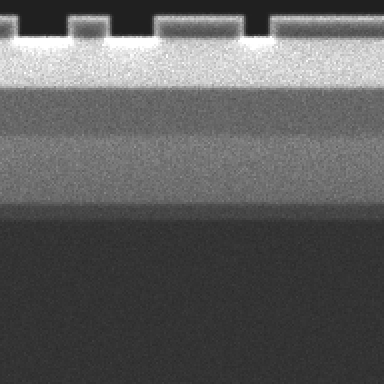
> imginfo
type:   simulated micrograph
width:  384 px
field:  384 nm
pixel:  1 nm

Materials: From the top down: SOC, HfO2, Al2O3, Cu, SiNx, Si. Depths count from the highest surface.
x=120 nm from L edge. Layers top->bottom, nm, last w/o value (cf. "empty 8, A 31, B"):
empty 22, HfO2 50, Al2O3 48, Cu 68, SiNx 16, Si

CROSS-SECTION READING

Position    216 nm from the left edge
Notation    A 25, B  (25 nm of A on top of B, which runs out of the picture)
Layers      SOC 22, HfO2 50, Al2O3 48, Cu 68, SiNx 16, Si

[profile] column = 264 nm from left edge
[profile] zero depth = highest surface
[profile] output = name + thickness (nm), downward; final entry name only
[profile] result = empty 22, HfO2 50, Al2O3 48, Cu 68, SiNx 16, Si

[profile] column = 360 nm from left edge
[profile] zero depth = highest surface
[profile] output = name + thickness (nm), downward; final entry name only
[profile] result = SOC 22, HfO2 50, Al2O3 48, Cu 68, SiNx 16, Si